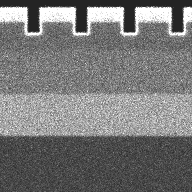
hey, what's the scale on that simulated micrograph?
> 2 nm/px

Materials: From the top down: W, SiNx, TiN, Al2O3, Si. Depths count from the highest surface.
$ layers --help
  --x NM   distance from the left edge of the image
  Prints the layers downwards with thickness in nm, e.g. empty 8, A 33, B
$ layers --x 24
W 28, SiNx 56, TiN 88, Al2O3 84, Si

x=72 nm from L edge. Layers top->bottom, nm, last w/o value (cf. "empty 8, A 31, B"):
empty 50, SiNx 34, TiN 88, Al2O3 84, Si